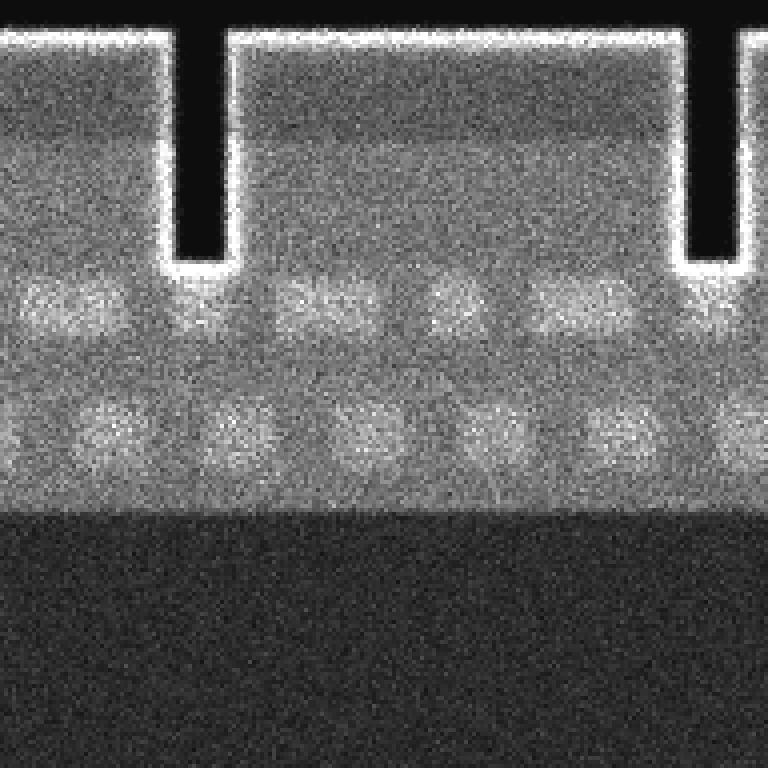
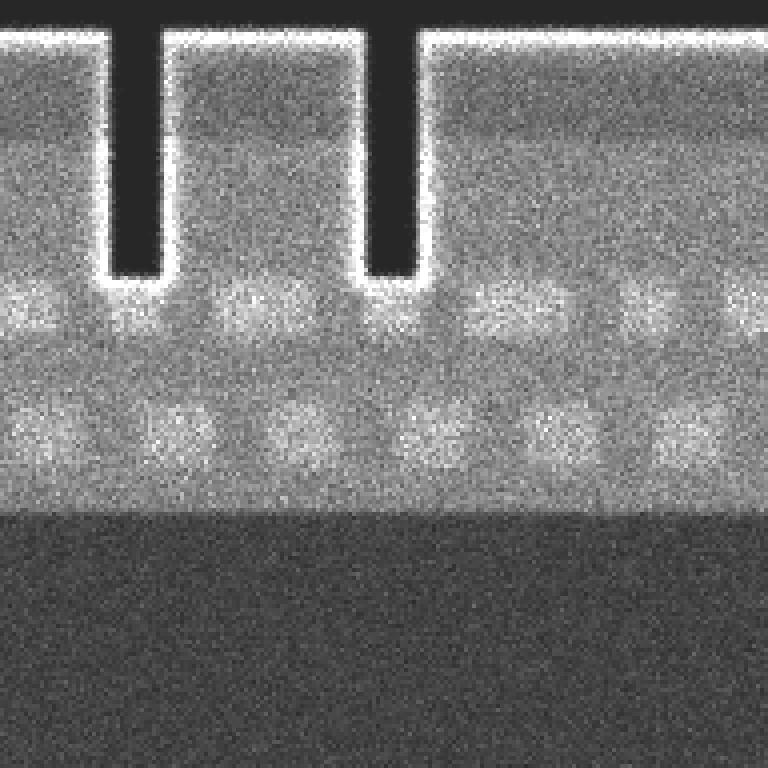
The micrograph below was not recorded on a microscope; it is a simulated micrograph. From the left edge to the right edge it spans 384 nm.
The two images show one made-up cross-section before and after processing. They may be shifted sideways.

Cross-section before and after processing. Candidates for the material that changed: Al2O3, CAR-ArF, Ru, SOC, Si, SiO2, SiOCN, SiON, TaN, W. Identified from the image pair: Al2O3 (removed).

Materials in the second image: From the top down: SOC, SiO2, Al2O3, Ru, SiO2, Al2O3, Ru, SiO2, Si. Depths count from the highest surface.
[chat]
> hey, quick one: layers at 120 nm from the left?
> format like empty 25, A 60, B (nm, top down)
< SOC 54, SiO2 62, Al2O3 8, Ru 28, SiO2 22, Al2O3 12, SiO2 54, Si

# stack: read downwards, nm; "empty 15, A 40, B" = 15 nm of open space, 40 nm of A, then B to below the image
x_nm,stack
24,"SOC 54, SiO2 62, Al2O3 8, Ru 28, SiO2 22, Al2O3 12, Ru 32, SiO2 22, Si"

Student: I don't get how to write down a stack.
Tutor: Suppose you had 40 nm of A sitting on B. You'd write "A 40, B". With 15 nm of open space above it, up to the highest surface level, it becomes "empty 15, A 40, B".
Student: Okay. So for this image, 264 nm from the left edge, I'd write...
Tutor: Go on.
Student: SOC 54, SiO2 62, Al2O3 8, Ru 28, SiO2 22, Al2O3 12, Ru 32, SiO2 22, Si